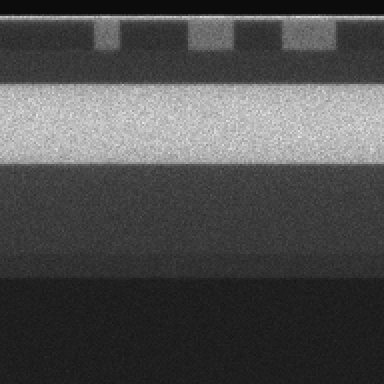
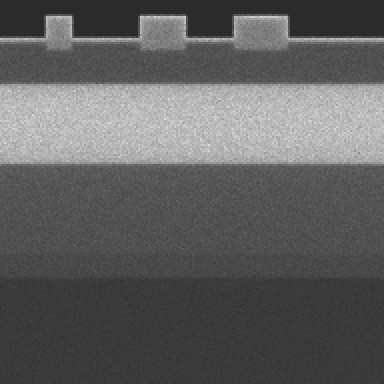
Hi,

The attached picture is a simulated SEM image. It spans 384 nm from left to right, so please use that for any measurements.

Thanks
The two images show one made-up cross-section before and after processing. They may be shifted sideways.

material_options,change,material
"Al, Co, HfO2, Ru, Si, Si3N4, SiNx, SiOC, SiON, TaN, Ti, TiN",removed,SiNx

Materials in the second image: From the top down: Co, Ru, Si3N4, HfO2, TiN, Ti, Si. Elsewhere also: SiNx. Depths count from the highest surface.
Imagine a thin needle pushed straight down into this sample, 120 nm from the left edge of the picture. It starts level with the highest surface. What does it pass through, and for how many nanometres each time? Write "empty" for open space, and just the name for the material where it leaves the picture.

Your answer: empty 22, SiNx 12, Si3N4 34, HfO2 80, TiN 90, Ti 24, Si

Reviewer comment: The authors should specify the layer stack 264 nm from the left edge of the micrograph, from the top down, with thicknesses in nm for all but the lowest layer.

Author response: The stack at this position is Co 24, Ru 10, Si3N4 34, HfO2 80, TiN 90, Ti 24, Si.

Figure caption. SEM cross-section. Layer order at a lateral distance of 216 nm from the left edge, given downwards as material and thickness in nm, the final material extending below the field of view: empty 22, SiNx 12, Si3N4 34, HfO2 80, TiN 90, Ti 24, Si